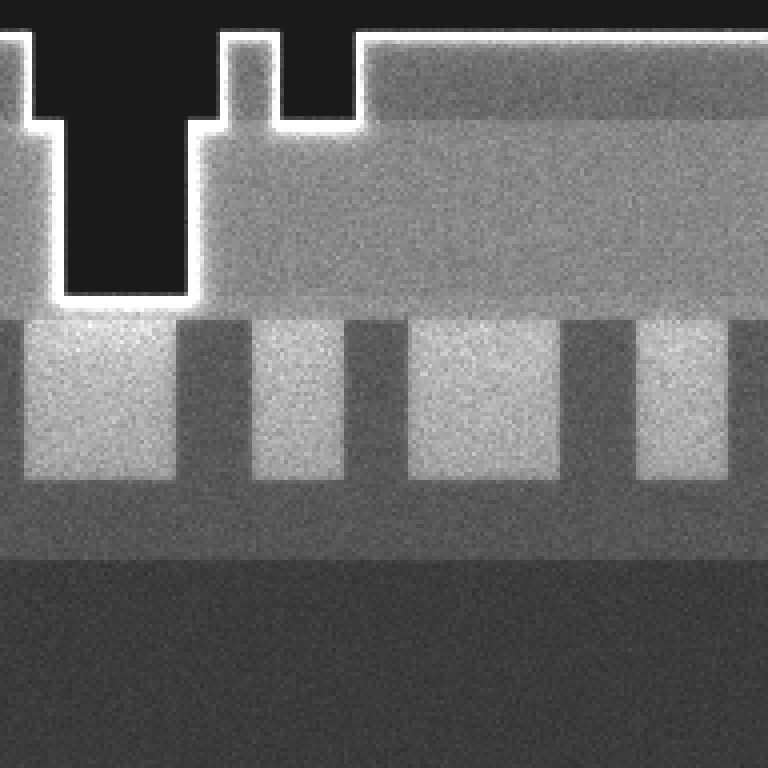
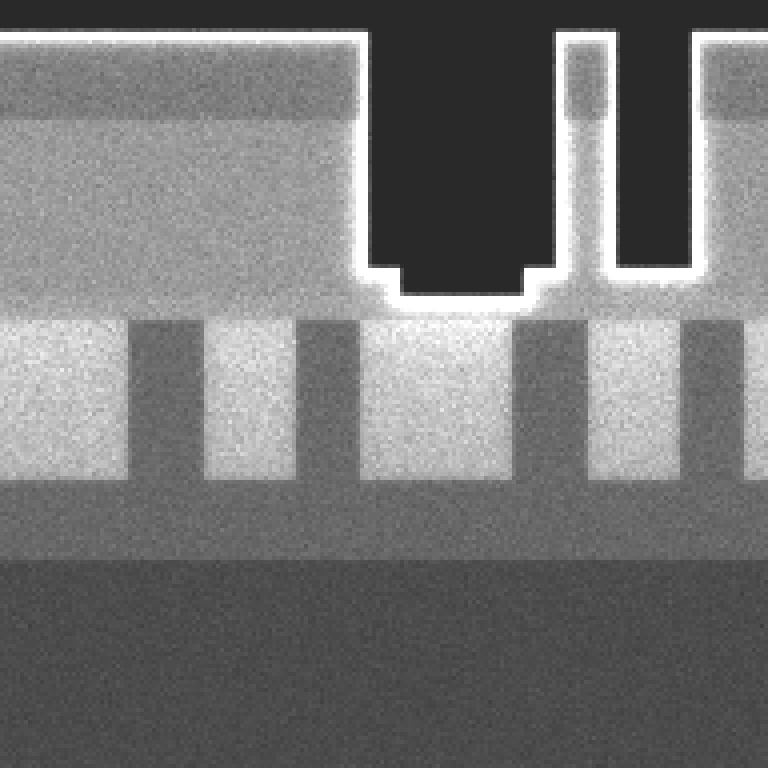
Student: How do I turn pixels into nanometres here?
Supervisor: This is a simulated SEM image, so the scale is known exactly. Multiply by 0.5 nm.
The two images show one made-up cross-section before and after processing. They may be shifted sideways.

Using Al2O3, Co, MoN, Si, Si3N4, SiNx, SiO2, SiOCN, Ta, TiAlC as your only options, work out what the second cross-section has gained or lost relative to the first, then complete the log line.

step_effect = removed SiO2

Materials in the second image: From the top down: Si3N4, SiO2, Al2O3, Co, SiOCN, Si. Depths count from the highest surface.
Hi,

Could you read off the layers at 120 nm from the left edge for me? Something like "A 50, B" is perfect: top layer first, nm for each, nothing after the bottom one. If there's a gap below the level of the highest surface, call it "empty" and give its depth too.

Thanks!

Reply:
Si3N4 44, SiO2 88, Al2O3 12, Co 80, SiOCN 40, Si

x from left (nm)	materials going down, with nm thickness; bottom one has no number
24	Si3N4 44, SiO2 88, Al2O3 12, Co 80, SiOCN 40, Si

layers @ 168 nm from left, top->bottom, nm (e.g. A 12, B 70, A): Si3N4 44, SiO2 88, Al2O3 12, SiOCN 120, Si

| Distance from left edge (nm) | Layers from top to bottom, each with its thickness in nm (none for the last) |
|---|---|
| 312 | empty 118, SiO2 14, Al2O3 12, Co 80, SiOCN 40, Si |